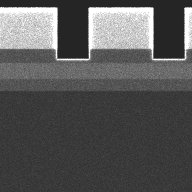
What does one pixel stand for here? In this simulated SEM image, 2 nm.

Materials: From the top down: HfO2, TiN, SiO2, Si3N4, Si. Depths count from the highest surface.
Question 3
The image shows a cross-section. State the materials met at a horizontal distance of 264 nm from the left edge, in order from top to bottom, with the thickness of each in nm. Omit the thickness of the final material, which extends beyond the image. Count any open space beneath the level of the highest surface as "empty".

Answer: HfO2 82, TiN 28, SiO2 32, Si3N4 24, Si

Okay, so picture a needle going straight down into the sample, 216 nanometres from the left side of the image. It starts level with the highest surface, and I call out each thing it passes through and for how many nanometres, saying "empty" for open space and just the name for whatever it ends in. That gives HfO2 82, TiN 28, SiO2 32, Si3N4 24, Si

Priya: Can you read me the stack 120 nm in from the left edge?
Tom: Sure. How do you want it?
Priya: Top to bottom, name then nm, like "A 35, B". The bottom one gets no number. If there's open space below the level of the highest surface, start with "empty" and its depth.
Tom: empty 102, TiN 8, SiO2 32, Si3N4 24, Si